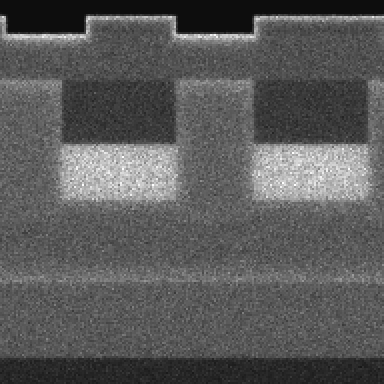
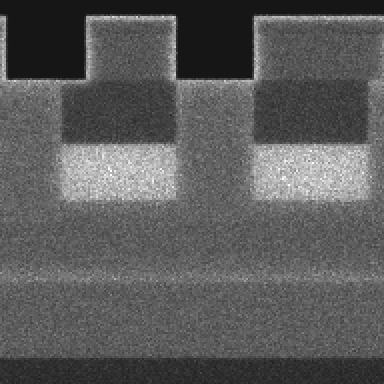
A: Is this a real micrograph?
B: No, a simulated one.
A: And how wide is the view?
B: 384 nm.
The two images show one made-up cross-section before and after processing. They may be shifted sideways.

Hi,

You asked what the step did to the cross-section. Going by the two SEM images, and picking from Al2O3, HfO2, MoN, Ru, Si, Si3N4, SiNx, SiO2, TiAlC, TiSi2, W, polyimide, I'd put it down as SiO2, removed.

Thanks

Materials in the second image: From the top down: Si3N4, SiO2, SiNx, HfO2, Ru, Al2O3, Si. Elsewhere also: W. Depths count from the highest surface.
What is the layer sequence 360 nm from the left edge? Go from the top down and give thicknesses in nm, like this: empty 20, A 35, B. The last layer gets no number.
Si3N4 18, SiO2 46, SiNx 64, HfO2 56, Ru 82, Al2O3 76, Si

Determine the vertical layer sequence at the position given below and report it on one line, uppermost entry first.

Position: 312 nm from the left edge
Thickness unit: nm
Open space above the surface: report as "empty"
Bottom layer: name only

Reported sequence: Si3N4 18, SiO2 46, SiNx 64, HfO2 56, Ru 82, Al2O3 76, Si